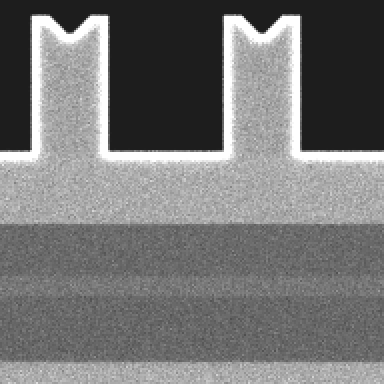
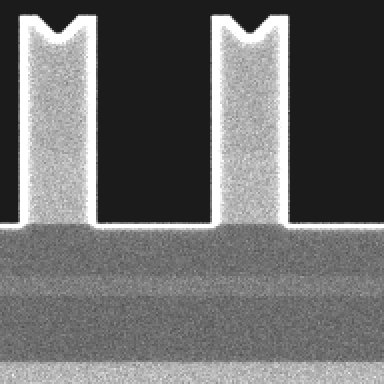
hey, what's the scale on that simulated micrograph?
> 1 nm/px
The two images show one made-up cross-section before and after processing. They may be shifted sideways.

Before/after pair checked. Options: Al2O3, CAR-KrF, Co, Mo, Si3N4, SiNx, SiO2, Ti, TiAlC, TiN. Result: removed Al2O3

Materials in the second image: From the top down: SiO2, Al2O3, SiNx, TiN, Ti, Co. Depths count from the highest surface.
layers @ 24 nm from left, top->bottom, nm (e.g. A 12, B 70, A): SiO2 136, Al2O3 72, SiNx 52, TiN 20, Ti 66, Co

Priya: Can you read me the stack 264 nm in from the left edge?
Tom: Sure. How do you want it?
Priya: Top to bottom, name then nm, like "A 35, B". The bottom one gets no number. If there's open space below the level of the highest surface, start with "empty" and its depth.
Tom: empty 6, SiO2 130, Al2O3 72, SiNx 52, TiN 20, Ti 66, Co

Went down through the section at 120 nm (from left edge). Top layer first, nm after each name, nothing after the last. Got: empty 208, SiNx 52, TiN 20, Ti 66, Co